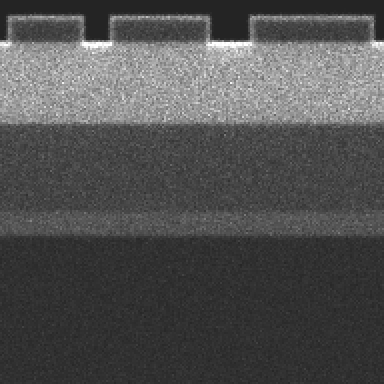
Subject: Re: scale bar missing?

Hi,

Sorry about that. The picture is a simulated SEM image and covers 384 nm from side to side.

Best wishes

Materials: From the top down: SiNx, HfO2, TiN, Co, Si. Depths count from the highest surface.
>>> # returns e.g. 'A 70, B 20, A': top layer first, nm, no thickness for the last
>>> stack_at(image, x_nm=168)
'SiNx 26, HfO2 82, TiN 88, Co 24, Si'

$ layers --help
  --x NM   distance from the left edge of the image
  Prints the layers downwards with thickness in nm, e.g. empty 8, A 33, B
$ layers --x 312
SiNx 26, HfO2 82, TiN 88, Co 24, Si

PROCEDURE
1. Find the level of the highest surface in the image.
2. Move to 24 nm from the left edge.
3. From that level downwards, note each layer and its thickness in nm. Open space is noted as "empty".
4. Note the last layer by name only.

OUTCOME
SiNx 26, HfO2 82, TiN 88, Co 24, Si